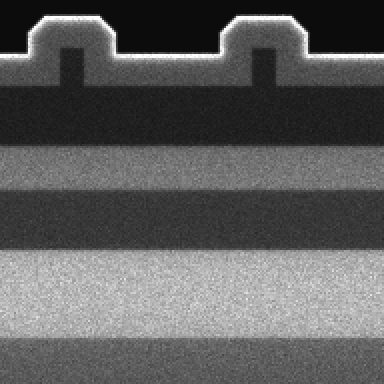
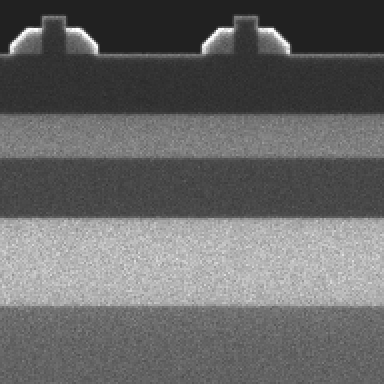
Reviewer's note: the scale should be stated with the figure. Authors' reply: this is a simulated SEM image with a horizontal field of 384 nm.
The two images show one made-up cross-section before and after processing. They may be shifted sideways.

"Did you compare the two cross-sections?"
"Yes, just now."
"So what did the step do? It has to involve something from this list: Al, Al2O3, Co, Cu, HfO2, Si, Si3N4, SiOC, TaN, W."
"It removed Al2O3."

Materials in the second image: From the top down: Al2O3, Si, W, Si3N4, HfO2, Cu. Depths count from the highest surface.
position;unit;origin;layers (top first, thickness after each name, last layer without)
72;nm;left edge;empty 12, Al2O3 26, Si 60, W 44, Si3N4 60, HfO2 88, Cu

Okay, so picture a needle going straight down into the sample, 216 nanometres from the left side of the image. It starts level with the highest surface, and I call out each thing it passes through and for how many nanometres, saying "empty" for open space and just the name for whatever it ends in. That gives empty 14, Al2O3 24, Si 60, W 44, Si3N4 60, HfO2 88, Cu